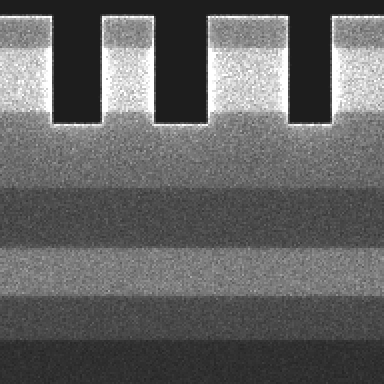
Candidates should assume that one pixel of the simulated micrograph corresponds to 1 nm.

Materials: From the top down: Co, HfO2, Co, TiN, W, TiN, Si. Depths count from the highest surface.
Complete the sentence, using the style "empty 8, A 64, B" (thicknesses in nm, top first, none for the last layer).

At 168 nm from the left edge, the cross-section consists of empty 108, Co 64, TiN 60, W 48, TiN 44, Si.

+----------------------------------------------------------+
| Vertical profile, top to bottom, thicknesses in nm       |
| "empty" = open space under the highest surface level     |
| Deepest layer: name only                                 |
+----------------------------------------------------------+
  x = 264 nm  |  Co 32, HfO2 64, Co 76, TiN 60, W 48, TiN 44, Si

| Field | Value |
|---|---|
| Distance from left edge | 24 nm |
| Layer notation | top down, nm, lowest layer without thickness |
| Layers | Co 32, HfO2 64, Co 76, TiN 60, W 48, TiN 44, Si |